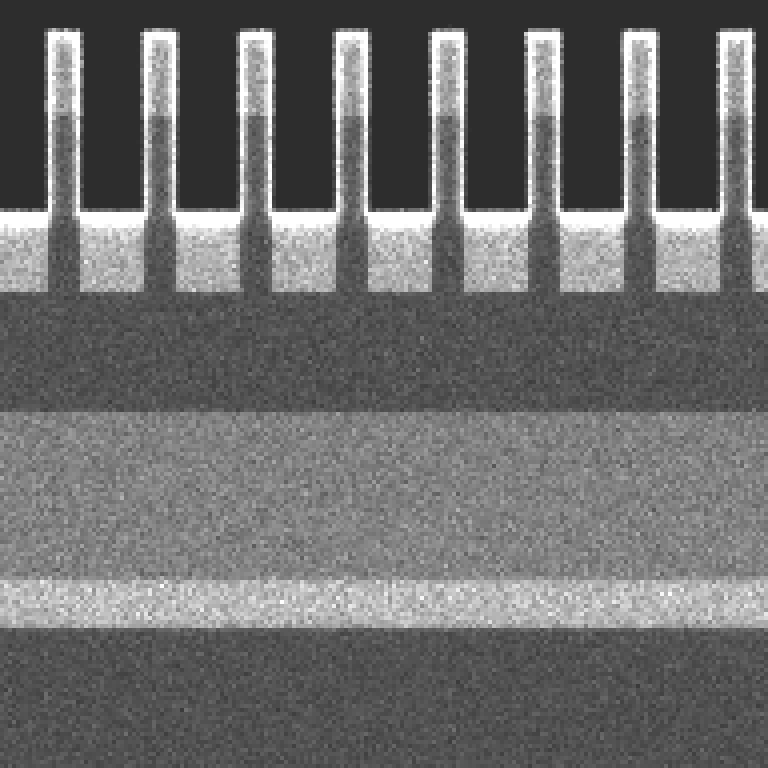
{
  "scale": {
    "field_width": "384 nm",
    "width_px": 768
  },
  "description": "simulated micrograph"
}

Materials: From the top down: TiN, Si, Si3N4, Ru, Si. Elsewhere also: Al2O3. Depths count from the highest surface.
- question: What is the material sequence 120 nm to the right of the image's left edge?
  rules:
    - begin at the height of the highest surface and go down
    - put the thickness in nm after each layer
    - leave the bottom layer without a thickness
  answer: TiN 42, Si 148, Si3N4 84, Ru 24, Si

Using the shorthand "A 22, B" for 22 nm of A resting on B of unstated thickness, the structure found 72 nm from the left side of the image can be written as TiN 42, Si 148, Si3N4 84, Ru 24, Si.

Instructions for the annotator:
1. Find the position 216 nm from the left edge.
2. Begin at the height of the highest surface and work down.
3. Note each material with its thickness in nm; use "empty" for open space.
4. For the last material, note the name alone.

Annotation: TiN 42, Si 148, Si3N4 84, Ru 24, Si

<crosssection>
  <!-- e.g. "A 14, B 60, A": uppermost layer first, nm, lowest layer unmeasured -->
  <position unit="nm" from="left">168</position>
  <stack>TiN 42, Si 148, Si3N4 84, Ru 24, Si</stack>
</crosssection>